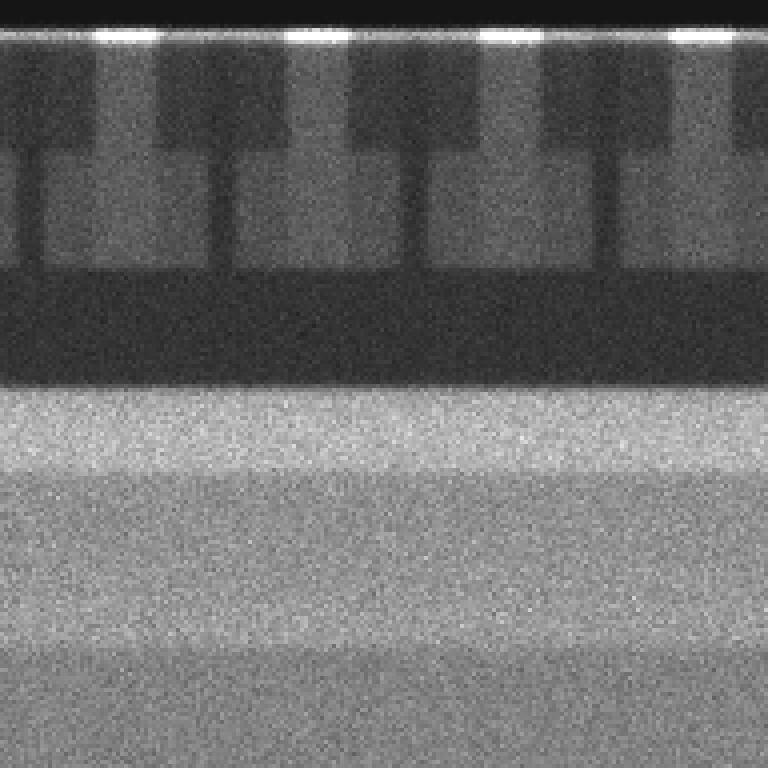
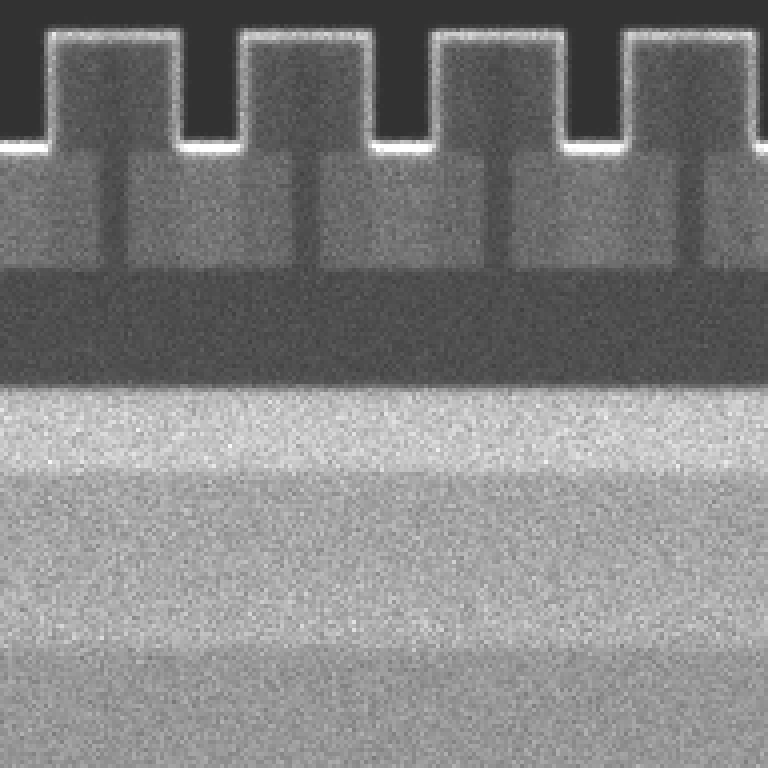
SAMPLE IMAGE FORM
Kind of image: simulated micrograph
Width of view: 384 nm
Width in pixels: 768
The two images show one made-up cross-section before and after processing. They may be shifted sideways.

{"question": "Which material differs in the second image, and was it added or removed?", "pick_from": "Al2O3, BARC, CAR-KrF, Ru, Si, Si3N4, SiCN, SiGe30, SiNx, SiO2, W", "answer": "Si3N4, removed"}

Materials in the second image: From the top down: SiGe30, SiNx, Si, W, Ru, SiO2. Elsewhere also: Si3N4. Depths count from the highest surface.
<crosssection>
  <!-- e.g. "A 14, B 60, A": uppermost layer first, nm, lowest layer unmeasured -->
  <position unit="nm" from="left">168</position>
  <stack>SiGe30 60, SiNx 58, Si 60, W 42, Ru 88, SiO2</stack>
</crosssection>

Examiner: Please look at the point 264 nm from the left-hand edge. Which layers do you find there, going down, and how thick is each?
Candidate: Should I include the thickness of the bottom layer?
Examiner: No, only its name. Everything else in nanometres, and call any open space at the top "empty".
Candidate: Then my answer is SiGe30 60, SiNx 58, Si 60, W 42, Ru 88, SiO2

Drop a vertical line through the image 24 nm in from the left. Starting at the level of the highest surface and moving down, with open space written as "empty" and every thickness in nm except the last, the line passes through SiGe30 60, SiNx 58, Si 60, W 42, Ru 88, SiO2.